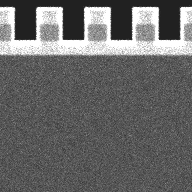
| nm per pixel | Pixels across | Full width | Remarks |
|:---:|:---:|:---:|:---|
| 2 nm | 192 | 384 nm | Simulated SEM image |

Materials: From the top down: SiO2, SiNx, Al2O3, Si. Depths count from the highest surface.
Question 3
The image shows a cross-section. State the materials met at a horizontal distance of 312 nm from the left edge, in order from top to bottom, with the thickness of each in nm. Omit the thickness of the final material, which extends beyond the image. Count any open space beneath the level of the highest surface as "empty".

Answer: SiO2 32, SiNx 34, Al2O3 28, Si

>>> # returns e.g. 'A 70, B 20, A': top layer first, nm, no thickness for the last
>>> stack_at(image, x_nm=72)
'empty 66, Al2O3 28, Si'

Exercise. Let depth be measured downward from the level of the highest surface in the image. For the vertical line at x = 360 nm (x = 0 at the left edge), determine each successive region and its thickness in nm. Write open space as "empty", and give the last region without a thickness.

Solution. empty 66, Al2O3 28, Si